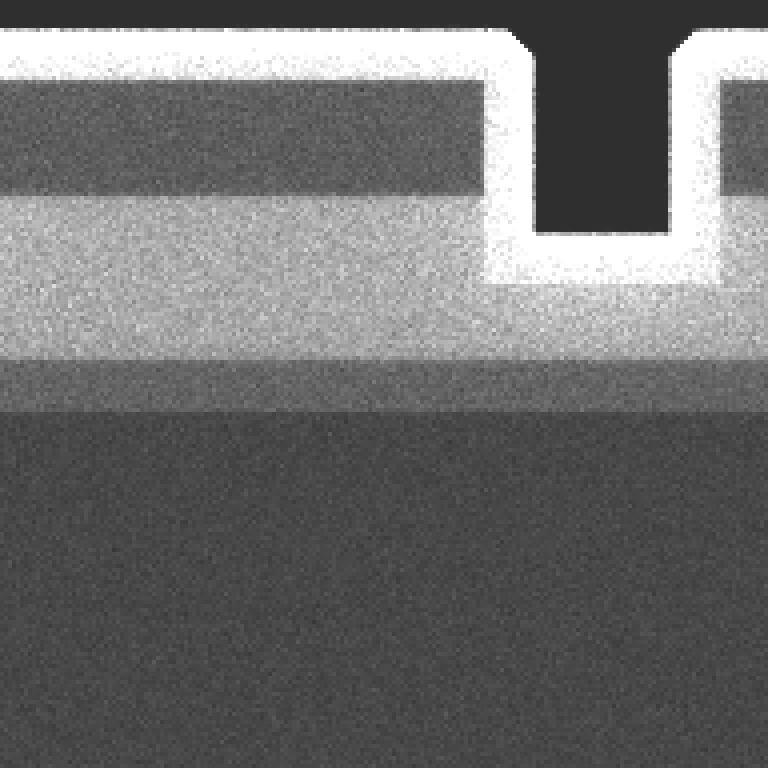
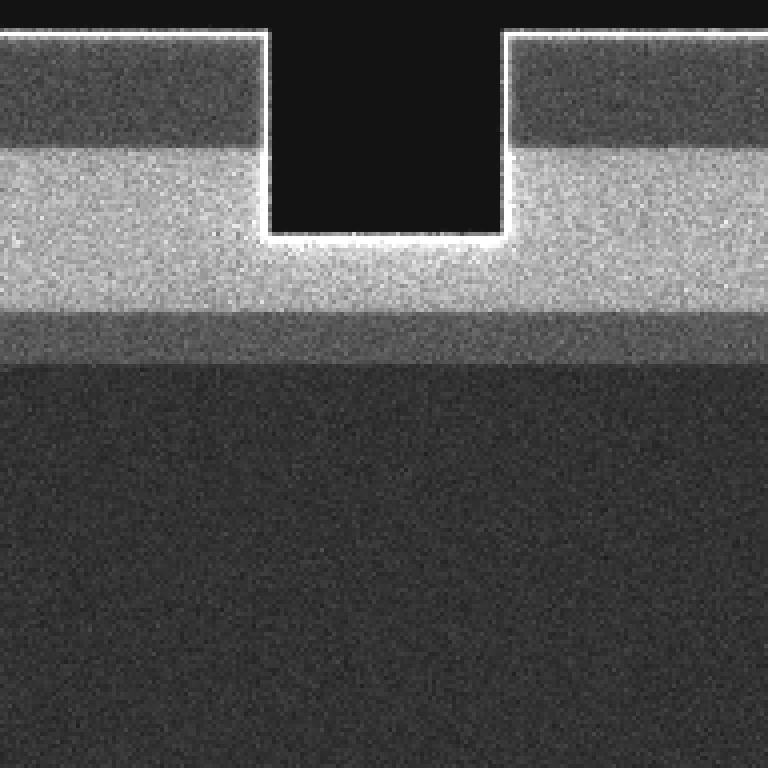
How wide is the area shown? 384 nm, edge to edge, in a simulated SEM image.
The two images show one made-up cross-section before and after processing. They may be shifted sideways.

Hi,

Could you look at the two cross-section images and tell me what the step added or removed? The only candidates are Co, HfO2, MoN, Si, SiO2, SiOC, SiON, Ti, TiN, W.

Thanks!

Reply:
removed HfO2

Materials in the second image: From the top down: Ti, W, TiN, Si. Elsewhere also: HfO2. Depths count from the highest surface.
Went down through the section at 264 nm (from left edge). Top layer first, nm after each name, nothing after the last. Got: Ti 58, W 82, TiN 26, Si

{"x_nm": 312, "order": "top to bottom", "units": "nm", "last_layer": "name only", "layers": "Ti 58, W 82, TiN 26, Si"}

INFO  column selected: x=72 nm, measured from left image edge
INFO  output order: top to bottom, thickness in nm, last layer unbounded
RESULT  Ti 58, W 82, TiN 26, Si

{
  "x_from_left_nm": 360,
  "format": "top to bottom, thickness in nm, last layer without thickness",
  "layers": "Ti 58, W 82, TiN 26, Si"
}